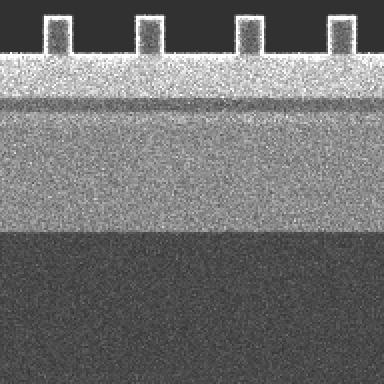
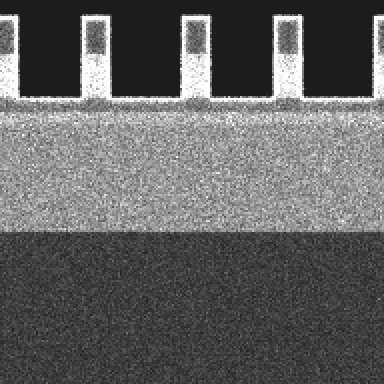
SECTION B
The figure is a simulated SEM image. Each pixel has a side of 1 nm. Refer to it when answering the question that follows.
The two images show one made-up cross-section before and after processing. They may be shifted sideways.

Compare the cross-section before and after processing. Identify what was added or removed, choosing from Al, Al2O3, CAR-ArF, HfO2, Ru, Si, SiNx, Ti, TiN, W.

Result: W removed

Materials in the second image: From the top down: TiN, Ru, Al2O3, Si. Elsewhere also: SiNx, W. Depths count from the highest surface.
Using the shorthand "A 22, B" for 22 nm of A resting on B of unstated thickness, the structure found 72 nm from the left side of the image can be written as empty 82, TiN 14, Ru 12, Al2O3 108, Si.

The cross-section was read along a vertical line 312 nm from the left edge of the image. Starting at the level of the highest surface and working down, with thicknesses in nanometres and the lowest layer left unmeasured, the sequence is empty 82, TiN 14, Ru 12, Al2O3 108, Si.